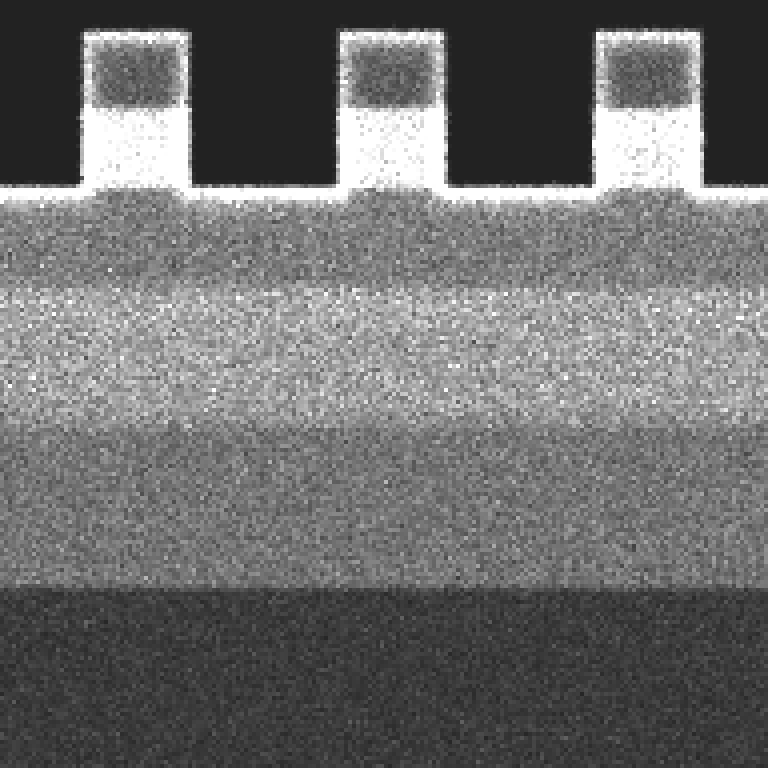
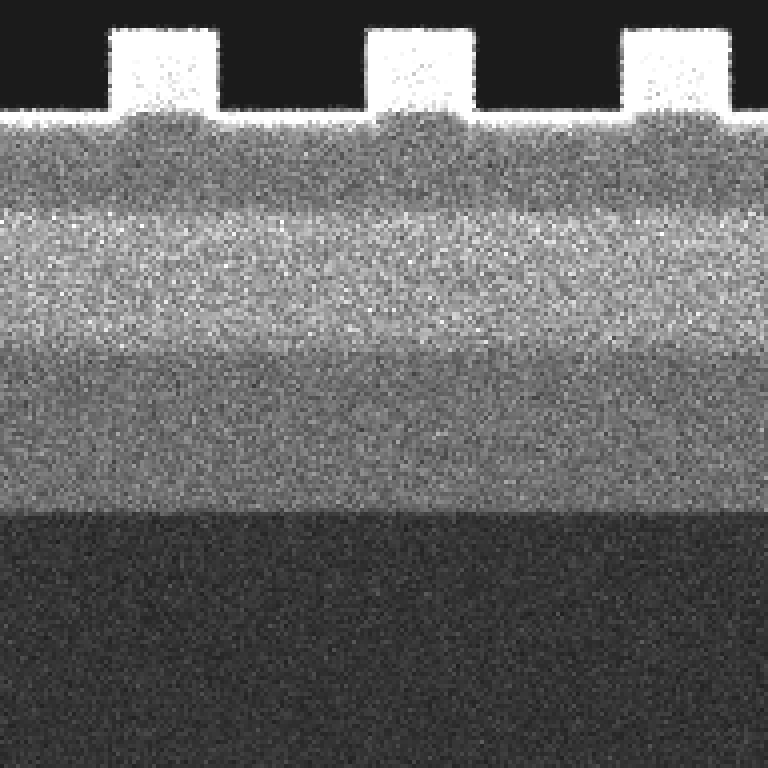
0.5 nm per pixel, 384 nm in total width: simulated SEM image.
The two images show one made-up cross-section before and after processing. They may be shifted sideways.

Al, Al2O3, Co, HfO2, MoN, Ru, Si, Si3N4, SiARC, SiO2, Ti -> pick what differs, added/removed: SiARC removed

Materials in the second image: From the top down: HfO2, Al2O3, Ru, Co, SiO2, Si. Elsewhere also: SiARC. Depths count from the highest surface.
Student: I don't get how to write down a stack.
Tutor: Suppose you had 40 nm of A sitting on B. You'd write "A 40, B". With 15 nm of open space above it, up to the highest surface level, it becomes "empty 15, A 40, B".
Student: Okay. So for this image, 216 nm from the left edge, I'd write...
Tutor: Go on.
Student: HfO2 40, Al2O3 50, Ru 60, Co 10, SiO2 80, Si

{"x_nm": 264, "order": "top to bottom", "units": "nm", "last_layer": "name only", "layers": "empty 40, Al2O3 50, Ru 60, Co 10, SiO2 80, Si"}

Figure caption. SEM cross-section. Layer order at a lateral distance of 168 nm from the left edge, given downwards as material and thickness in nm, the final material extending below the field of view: empty 40, Al2O3 50, Ru 60, Co 10, SiO2 80, Si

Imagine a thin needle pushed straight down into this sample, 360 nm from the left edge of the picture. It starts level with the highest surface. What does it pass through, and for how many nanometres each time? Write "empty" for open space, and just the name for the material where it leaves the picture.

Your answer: HfO2 40, Al2O3 50, Ru 60, Co 10, SiO2 80, Si